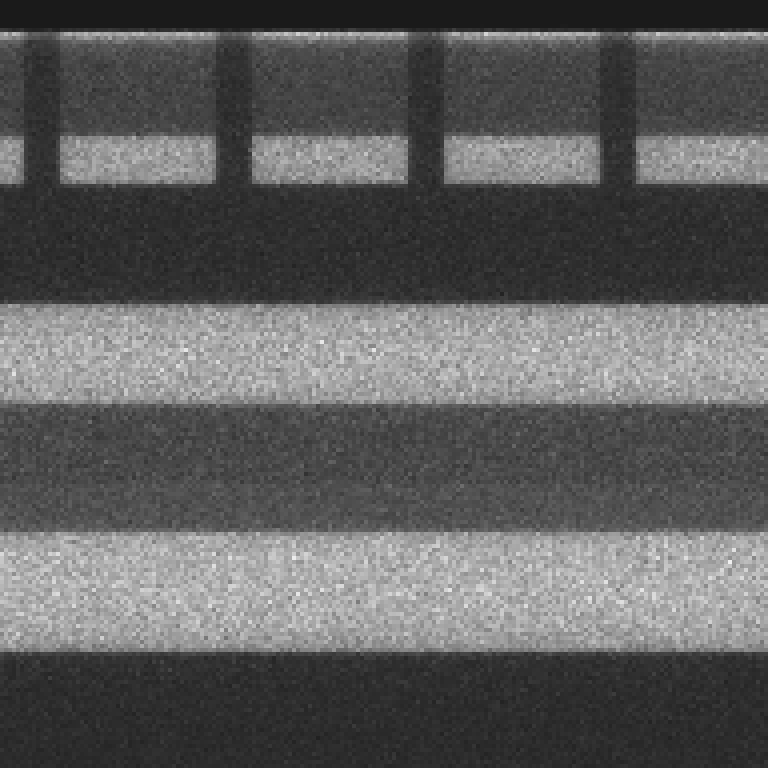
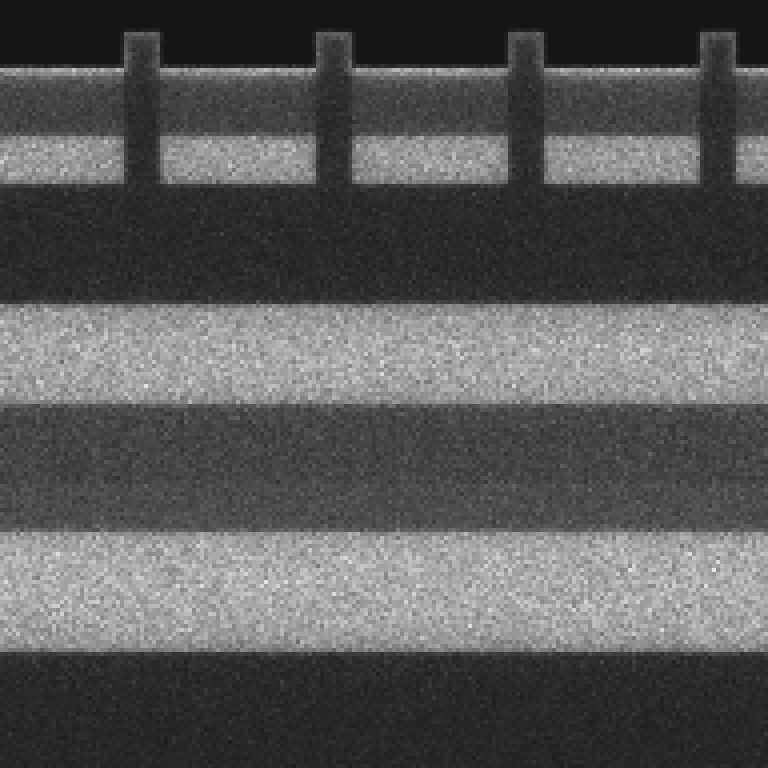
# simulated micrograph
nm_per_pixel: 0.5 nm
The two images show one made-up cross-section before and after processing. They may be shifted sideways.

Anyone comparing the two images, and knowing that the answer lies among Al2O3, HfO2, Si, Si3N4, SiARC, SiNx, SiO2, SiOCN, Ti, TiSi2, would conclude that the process removed Si3N4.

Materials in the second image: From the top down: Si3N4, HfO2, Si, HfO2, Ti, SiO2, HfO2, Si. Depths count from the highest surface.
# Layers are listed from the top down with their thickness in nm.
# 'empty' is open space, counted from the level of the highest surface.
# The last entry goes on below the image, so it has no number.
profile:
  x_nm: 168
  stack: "Si 136, HfO2 50, Ti 40, SiO2 24, HfO2 60, Si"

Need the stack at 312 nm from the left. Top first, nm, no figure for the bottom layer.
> empty 18, Si3N4 34, HfO2 24, Si 60, HfO2 50, Ti 40, SiO2 24, HfO2 60, Si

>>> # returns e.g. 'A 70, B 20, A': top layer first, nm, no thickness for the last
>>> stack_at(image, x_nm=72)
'Si 136, HfO2 50, Ti 40, SiO2 24, HfO2 60, Si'